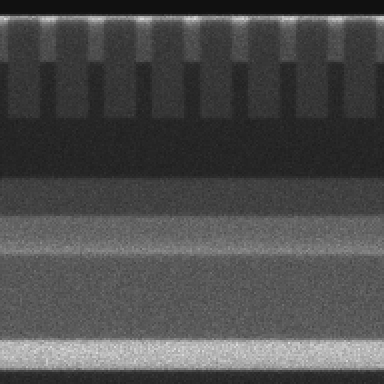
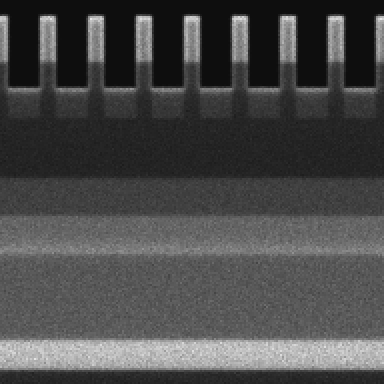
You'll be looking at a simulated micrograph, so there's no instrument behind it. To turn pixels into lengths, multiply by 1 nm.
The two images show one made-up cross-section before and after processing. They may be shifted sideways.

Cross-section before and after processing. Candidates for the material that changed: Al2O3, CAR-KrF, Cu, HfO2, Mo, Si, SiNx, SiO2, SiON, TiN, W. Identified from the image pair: SiNx (removed).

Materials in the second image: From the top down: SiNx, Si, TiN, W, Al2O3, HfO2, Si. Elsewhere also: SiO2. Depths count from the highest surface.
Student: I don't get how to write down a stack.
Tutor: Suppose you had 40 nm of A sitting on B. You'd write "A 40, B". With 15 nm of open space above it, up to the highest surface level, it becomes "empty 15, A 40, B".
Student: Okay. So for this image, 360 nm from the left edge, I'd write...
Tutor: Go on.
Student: empty 72, SiNx 30, Si 60, TiN 38, W 38, Al2O3 86, HfO2 30, Si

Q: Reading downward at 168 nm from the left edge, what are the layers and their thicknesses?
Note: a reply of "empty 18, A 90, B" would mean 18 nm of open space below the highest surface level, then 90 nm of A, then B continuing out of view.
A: empty 72, SiNx 30, Si 60, TiN 38, W 38, Al2O3 86, HfO2 30, Si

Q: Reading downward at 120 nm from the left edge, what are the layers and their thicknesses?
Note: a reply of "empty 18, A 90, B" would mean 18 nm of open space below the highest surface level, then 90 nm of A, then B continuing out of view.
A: empty 72, SiNx 30, Si 60, TiN 38, W 38, Al2O3 86, HfO2 30, Si